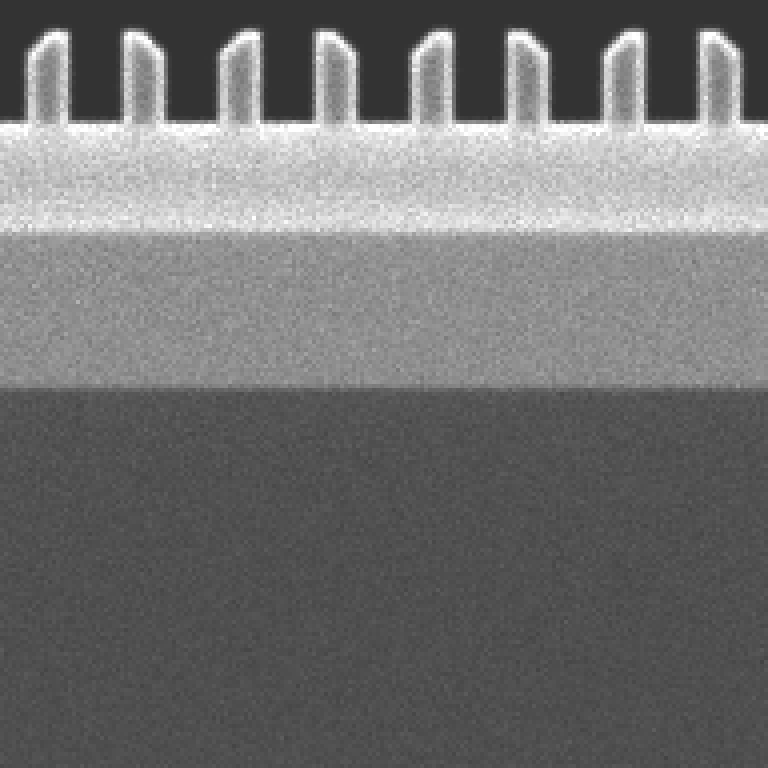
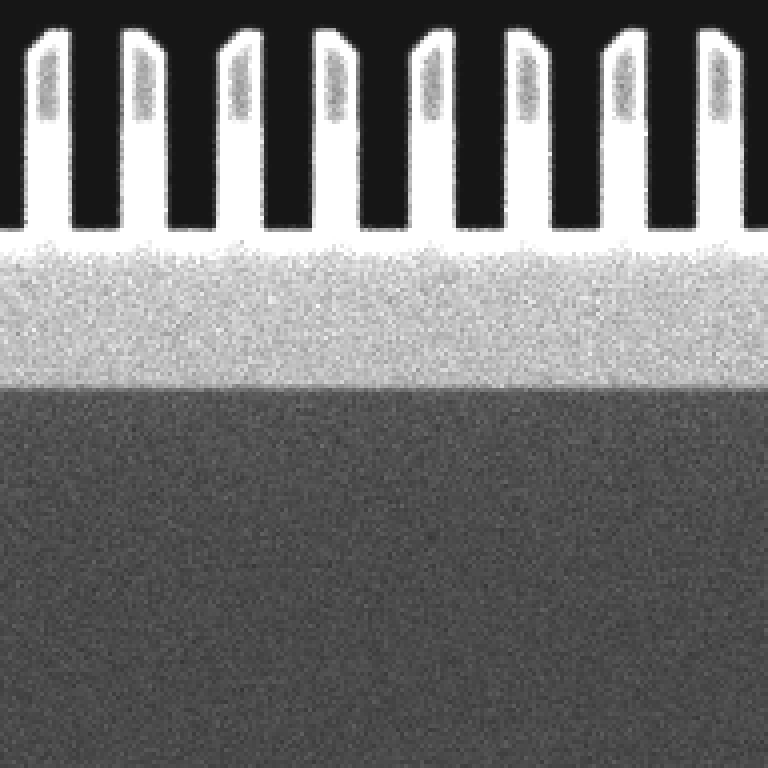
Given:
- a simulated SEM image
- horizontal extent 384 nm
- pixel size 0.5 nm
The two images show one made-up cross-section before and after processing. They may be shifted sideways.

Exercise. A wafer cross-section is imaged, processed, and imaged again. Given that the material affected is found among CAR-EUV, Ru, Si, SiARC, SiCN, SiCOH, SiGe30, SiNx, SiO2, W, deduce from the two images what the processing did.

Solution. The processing removed W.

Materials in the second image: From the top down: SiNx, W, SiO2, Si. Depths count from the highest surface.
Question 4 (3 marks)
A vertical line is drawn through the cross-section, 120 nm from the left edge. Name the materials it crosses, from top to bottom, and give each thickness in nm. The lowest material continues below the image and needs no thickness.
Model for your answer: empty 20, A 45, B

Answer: SiNx 46, W 54, SiO2 78, Si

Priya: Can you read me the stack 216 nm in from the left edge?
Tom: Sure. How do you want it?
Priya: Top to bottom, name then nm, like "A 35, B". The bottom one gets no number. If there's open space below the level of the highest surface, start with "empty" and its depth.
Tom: SiNx 46, W 54, SiO2 78, Si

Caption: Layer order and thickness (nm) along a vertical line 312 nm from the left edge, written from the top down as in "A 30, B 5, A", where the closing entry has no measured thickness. SiNx 46, W 54, SiO2 78, Si